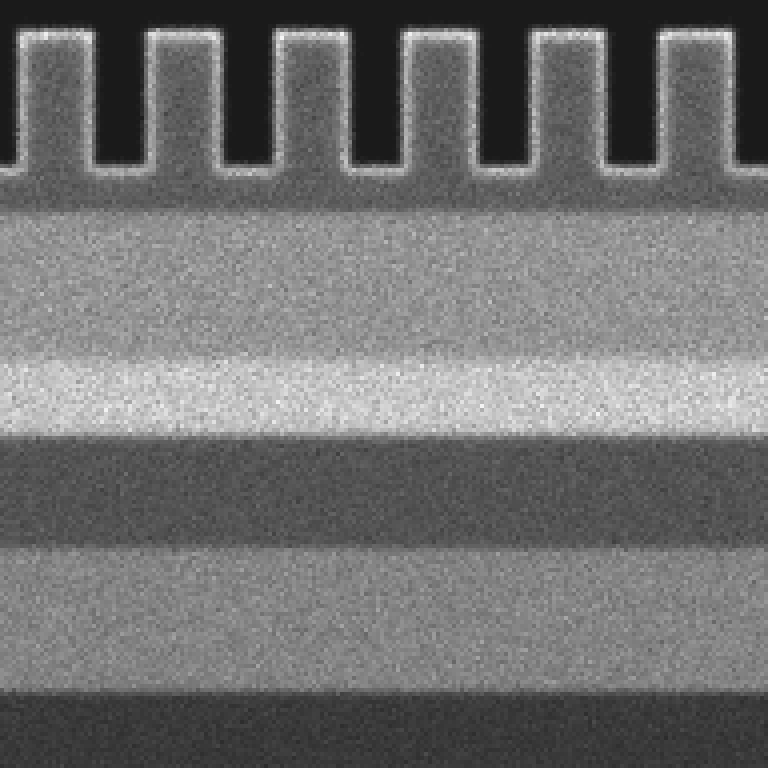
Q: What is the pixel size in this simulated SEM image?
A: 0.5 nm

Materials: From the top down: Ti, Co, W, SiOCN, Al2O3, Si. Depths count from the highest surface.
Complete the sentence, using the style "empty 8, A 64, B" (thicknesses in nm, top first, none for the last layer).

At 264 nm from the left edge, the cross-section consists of empty 68, Ti 22, Co 74, W 38, SiOCN 56, Al2O3 72, Si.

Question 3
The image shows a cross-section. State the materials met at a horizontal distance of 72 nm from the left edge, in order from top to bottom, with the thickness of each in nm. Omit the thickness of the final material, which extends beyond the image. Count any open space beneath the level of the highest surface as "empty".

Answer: empty 68, Ti 22, Co 74, W 38, SiOCN 56, Al2O3 72, Si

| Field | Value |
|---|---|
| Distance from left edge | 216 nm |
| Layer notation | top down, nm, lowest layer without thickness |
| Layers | Ti 90, Co 74, W 38, SiOCN 56, Al2O3 72, Si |